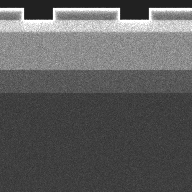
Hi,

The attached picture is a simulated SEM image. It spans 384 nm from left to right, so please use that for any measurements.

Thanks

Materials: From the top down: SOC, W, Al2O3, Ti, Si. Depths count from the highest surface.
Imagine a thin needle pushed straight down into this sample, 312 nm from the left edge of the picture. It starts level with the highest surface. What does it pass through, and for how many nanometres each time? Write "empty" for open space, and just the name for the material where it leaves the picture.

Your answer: SOC 24, W 24, Al2O3 76, Ti 46, Si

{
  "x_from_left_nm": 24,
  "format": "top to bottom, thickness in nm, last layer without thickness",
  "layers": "SOC 24, W 24, Al2O3 76, Ti 46, Si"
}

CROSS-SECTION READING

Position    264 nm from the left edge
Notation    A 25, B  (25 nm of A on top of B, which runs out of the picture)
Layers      empty 24, W 24, Al2O3 76, Ti 46, Si